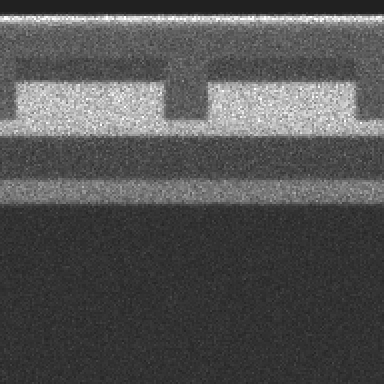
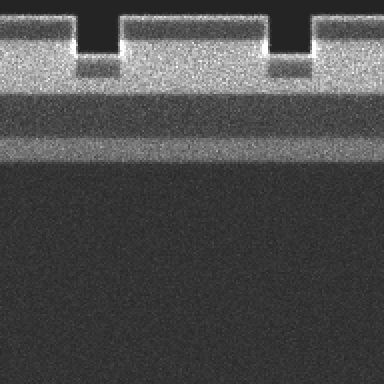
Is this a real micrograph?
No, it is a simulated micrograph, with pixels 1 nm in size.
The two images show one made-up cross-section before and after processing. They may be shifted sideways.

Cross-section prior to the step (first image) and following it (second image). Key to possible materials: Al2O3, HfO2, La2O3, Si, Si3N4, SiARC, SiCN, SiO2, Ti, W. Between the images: SiO2 was removed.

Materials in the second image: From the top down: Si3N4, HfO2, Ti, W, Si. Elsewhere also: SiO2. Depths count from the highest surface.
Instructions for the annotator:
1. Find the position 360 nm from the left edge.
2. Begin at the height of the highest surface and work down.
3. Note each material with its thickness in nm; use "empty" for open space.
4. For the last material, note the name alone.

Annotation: Si3N4 24, HfO2 54, Ti 44, W 24, Si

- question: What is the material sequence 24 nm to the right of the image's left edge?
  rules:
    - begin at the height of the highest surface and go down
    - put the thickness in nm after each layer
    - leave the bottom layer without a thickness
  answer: Si3N4 24, HfO2 54, Ti 44, W 24, Si